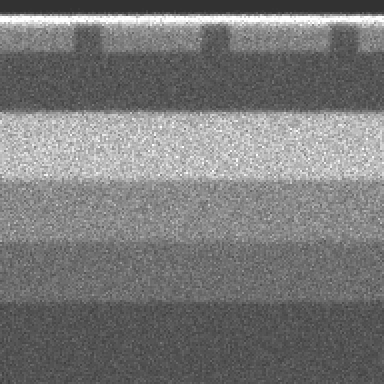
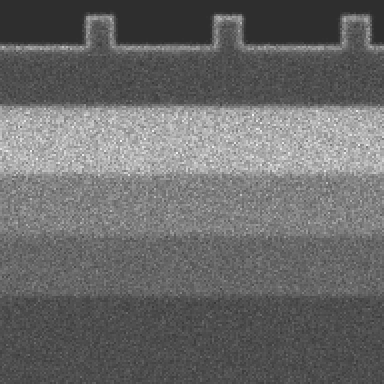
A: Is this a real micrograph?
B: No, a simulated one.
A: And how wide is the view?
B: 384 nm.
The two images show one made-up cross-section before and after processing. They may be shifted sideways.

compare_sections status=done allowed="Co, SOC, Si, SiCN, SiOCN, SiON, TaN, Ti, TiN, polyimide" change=removed material="SOC"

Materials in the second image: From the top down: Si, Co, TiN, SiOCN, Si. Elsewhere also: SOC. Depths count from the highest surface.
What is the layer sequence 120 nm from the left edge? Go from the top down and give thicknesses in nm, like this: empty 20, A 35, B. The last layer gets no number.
empty 30, Si 60, Co 68, TiN 62, SiOCN 60, Si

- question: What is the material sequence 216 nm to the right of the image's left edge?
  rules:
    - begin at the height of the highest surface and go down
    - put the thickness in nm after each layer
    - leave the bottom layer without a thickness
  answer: Si 90, Co 68, TiN 62, SiOCN 60, Si